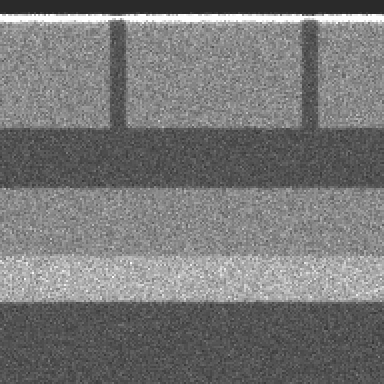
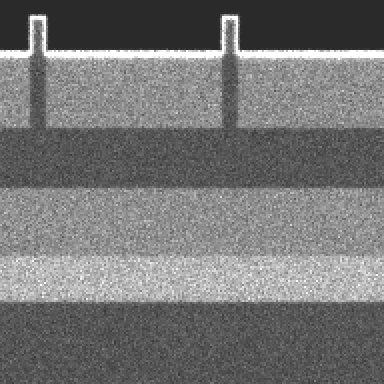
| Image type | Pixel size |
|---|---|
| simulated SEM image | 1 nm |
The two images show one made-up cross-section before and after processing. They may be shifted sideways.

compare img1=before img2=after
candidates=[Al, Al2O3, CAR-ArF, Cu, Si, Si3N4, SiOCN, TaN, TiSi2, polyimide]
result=removed:Si3N4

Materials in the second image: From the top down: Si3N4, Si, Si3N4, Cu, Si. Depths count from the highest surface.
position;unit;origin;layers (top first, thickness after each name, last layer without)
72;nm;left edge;empty 36, Si3N4 76, Si 60, Si3N4 68, Cu 46, Si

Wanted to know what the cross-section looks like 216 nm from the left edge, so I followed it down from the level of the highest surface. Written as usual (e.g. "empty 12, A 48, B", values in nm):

empty 36, Si3N4 76, Si 60, Si3N4 68, Cu 46, Si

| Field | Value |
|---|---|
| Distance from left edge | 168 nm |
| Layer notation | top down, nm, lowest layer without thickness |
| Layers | empty 36, Si3N4 76, Si 60, Si3N4 68, Cu 46, Si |